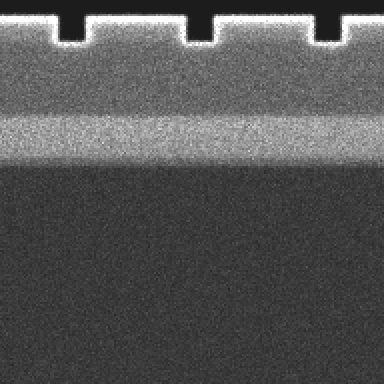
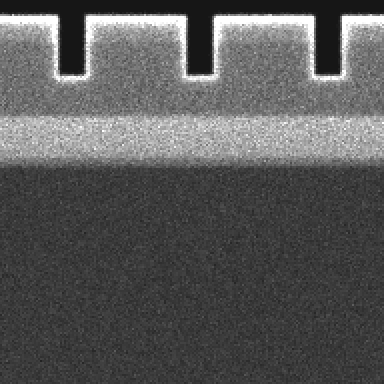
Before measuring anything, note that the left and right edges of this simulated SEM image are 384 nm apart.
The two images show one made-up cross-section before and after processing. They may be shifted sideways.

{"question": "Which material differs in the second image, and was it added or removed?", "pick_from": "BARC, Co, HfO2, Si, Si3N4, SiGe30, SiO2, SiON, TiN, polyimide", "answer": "Si3N4, removed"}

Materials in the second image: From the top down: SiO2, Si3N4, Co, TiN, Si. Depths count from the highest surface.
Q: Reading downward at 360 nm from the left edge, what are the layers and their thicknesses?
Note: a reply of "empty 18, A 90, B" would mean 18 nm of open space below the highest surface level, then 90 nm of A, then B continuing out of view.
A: SiO2 26, Si3N4 74, Co 42, TiN 8, Si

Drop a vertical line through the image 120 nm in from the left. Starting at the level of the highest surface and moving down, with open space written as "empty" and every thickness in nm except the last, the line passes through SiO2 26, Si3N4 74, Co 42, TiN 8, Si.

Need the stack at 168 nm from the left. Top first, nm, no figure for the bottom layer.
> SiO2 26, Si3N4 74, Co 42, TiN 8, Si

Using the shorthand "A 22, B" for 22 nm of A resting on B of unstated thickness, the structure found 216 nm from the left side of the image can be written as SiO2 26, Si3N4 74, Co 42, TiN 8, Si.